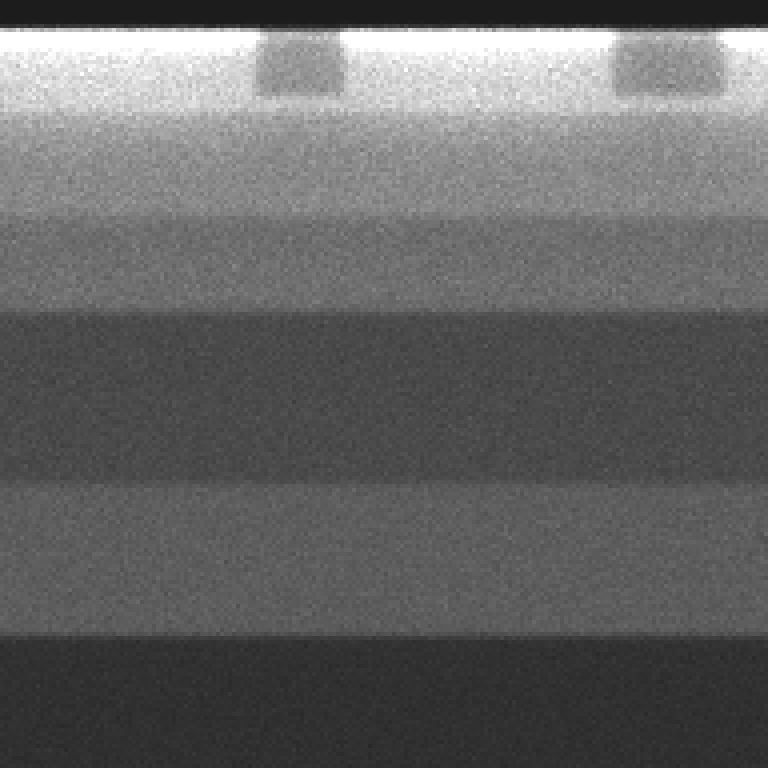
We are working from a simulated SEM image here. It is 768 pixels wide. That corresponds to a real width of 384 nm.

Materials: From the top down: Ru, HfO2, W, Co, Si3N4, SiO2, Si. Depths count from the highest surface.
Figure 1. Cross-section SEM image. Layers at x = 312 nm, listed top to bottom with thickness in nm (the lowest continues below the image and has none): Ru 32, HfO2 8, W 52, Co 48, Si3N4 86, SiO2 76, Si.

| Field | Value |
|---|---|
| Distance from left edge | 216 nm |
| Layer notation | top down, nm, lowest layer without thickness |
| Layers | HfO2 40, W 52, Co 48, Si3N4 86, SiO2 76, Si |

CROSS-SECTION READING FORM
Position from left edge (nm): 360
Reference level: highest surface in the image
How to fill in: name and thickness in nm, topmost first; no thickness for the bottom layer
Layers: Ru 32, HfO2 8, W 52, Co 48, Si3N4 86, SiO2 76, Si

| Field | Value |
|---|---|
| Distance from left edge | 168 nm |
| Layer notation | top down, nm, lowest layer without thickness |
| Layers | Ru 32, HfO2 8, W 52, Co 48, Si3N4 86, SiO2 76, Si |